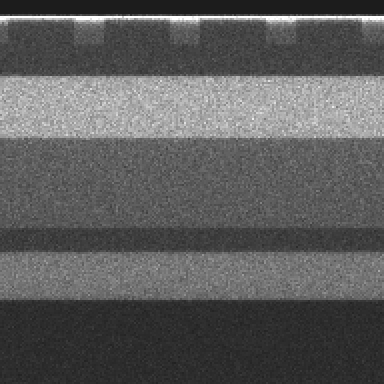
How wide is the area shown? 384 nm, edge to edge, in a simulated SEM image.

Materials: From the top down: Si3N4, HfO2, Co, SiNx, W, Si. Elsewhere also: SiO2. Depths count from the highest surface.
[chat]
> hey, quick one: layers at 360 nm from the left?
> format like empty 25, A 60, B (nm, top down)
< Si3N4 60, HfO2 62, Co 90, SiNx 24, W 48, Si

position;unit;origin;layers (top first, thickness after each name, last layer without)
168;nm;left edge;Si3N4 60, HfO2 62, Co 90, SiNx 24, W 48, Si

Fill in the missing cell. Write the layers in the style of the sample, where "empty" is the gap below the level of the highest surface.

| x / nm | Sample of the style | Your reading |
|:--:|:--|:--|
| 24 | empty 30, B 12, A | Si3N4 60, HfO2 62, Co 90, SiNx 24, W 48, Si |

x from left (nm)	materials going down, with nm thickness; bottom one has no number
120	Si3N4 60, HfO2 62, Co 90, SiNx 24, W 48, Si